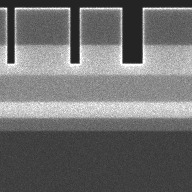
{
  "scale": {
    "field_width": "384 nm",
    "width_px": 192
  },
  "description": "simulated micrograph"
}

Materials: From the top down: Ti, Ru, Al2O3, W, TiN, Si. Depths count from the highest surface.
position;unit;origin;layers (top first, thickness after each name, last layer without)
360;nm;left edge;Ti 74, Ru 60, Al2O3 54, W 32, TiN 26, Si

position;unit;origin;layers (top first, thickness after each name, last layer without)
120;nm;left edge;Ti 74, Ru 60, Al2O3 54, W 32, TiN 26, Si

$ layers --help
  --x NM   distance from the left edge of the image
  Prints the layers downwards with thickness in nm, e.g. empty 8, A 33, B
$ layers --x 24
empty 112, Ru 22, Al2O3 54, W 32, TiN 26, Si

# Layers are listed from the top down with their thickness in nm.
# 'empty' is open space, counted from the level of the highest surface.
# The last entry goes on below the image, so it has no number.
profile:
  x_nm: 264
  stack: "empty 112, Ru 22, Al2O3 54, W 32, TiN 26, Si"